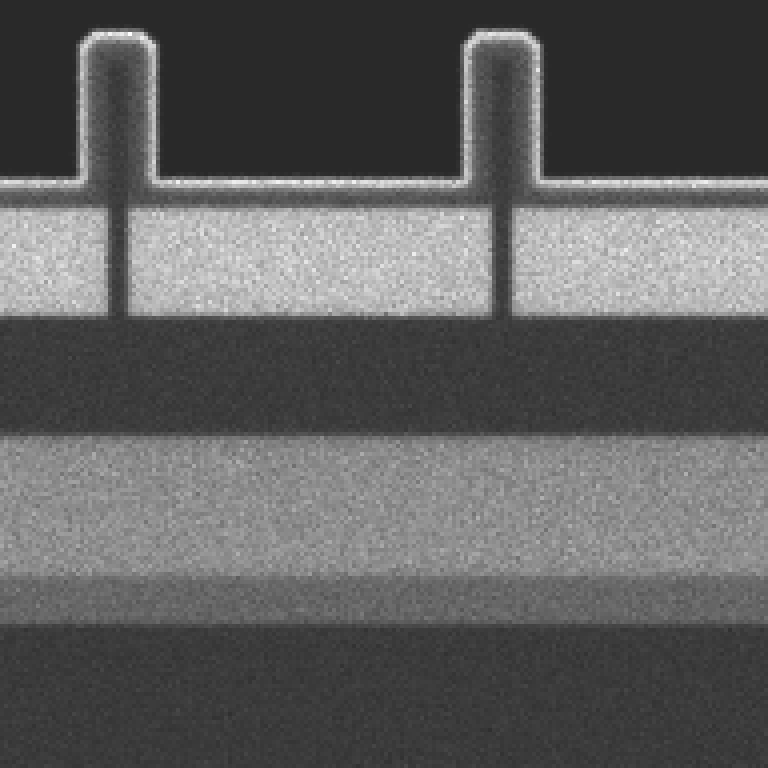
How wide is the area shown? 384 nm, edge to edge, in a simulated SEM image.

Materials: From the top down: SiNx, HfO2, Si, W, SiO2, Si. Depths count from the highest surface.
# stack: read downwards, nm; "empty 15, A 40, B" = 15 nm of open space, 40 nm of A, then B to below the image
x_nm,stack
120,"empty 74, SiNx 14, HfO2 54, Si 60, W 70, SiO2 24, Si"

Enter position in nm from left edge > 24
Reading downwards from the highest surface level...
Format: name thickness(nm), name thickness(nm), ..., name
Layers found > empty 74, SiNx 14, HfO2 54, Si 60, W 70, SiO2 24, Si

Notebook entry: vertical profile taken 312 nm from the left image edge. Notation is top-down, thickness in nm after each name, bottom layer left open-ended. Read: empty 74, SiNx 14, HfO2 54, Si 60, W 70, SiO2 24, Si